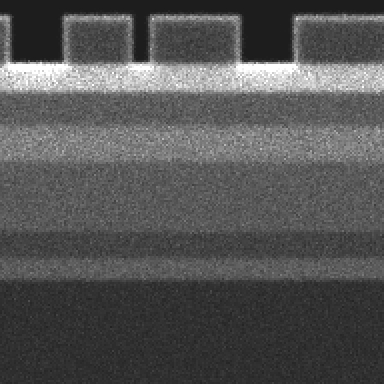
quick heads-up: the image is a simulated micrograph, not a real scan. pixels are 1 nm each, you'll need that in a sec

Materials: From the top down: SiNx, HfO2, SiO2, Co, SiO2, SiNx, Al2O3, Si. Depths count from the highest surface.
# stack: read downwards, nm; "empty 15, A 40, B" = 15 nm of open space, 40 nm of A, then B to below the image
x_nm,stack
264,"empty 48, HfO2 28, SiO2 34, Co 36, SiO2 70, SiNx 26, Al2O3 22, Si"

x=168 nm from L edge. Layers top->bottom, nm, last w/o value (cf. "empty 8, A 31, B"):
SiNx 48, HfO2 28, SiO2 34, Co 36, SiO2 70, SiNx 26, Al2O3 22, Si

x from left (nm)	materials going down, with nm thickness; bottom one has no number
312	SiNx 48, HfO2 28, SiO2 34, Co 36, SiO2 70, SiNx 26, Al2O3 22, Si